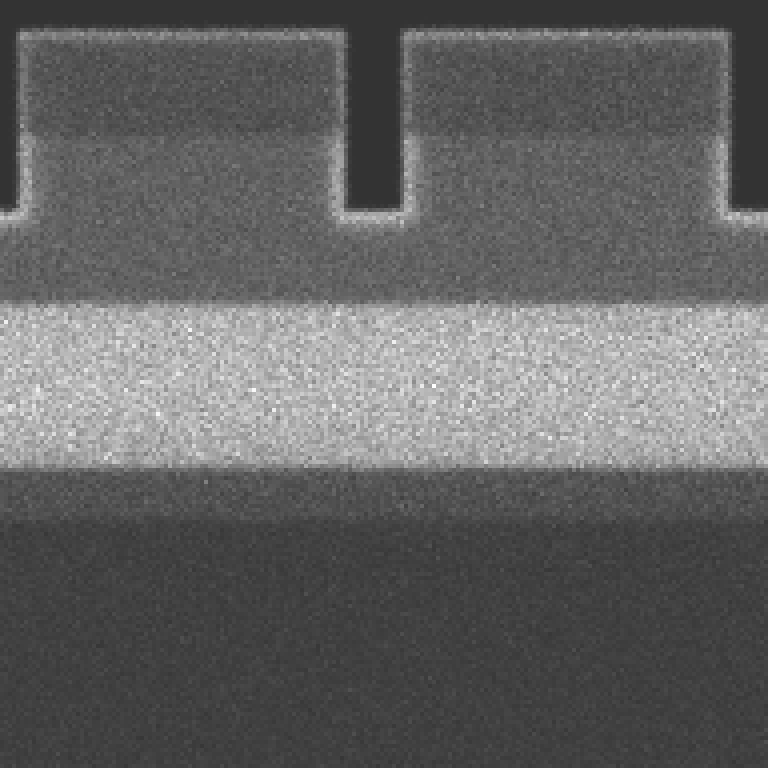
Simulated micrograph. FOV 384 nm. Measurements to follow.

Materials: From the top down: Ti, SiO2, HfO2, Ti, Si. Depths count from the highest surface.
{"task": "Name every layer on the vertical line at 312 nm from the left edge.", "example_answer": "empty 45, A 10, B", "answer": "Ti 52, SiO2 84, HfO2 82, Ti 26, Si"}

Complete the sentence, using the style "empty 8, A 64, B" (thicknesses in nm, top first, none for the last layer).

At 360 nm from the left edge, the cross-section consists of Ti 52, SiO2 84, HfO2 82, Ti 26, Si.